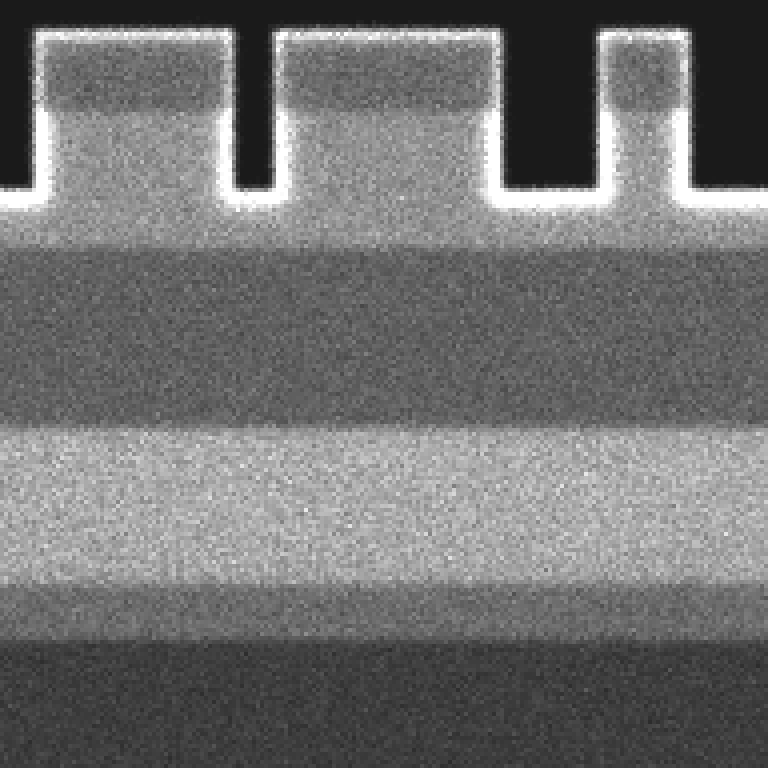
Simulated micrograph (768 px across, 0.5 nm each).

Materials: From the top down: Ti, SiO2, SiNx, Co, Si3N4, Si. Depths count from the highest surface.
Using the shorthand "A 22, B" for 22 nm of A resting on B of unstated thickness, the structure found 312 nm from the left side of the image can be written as Ti 40, SiO2 68, SiNx 90, Co 78, Si3N4 28, Si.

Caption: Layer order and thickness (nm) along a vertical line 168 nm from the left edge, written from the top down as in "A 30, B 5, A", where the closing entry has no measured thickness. Ti 40, SiO2 68, SiNx 90, Co 78, Si3N4 28, Si